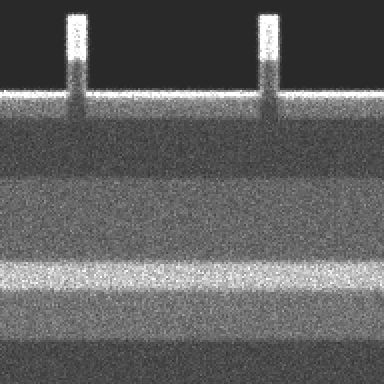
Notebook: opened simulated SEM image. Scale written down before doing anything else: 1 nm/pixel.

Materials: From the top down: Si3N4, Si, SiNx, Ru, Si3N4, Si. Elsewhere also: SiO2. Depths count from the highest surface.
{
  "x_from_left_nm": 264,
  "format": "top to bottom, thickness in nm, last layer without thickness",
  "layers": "SiO2 44, Si 118, SiNx 84, Ru 28, Si3N4 50, Si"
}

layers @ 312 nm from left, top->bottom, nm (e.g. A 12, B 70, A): empty 76, Si3N4 26, Si 60, SiNx 84, Ru 28, Si3N4 50, Si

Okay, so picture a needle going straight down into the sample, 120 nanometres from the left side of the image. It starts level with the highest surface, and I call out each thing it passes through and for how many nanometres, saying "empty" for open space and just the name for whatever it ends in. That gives empty 76, Si3N4 26, Si 60, SiNx 84, Ru 28, Si3N4 50, Si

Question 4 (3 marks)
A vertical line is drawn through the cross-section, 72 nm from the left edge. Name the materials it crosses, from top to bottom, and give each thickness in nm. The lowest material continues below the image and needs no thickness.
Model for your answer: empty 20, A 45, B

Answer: SiO2 44, Si 118, SiNx 84, Ru 28, Si3N4 50, Si